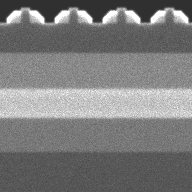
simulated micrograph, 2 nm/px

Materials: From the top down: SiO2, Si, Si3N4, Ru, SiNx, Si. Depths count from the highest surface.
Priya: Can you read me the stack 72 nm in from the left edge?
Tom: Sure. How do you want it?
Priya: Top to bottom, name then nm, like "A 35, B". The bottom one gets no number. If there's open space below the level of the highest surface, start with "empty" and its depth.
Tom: empty 6, SiO2 24, Si 60, Si3N4 72, Ru 58, SiNx 68, Si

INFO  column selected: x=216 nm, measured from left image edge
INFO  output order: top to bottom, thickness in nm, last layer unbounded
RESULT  empty 10, SiO2 20, Si 60, Si3N4 72, Ru 58, SiNx 68, Si